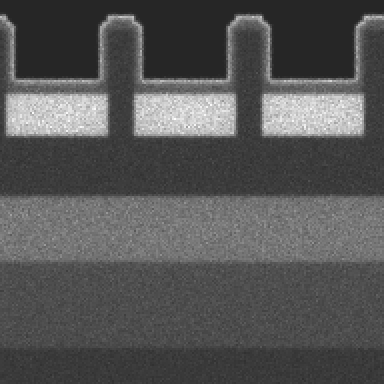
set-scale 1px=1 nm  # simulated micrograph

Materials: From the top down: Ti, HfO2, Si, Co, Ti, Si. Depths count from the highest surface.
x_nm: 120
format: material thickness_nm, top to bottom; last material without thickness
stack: Ti 14, Si 166, Co 66, Ti 86, Si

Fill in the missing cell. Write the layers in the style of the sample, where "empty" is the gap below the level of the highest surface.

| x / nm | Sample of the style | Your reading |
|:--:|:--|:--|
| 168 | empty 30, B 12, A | empty 64, Ti 14, HfO2 42, Si 60, Co 66, Ti 86, Si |